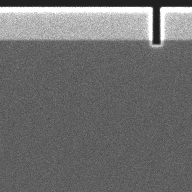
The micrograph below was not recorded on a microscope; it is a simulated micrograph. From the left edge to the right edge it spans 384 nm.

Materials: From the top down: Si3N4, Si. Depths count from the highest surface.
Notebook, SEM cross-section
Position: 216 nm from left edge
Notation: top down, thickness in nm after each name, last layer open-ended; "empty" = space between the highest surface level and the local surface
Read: Si3N4 64, Si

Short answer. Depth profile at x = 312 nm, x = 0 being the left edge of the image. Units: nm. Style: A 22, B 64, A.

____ empty 74, Si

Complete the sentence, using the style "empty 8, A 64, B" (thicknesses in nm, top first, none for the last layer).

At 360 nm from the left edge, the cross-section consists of Si3N4 64, Si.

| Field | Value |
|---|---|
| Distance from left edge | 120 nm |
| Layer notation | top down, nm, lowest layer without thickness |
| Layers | Si3N4 64, Si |